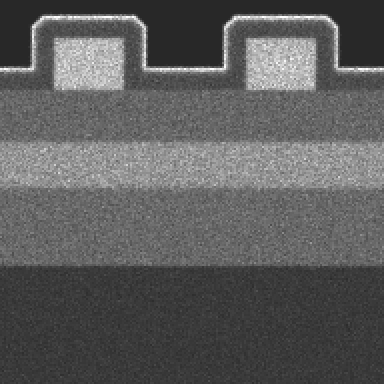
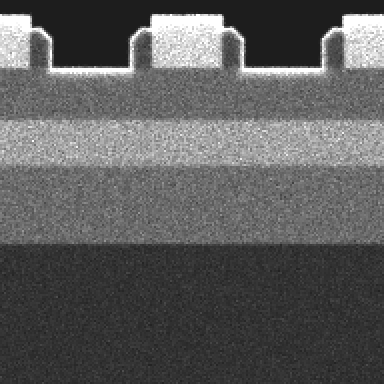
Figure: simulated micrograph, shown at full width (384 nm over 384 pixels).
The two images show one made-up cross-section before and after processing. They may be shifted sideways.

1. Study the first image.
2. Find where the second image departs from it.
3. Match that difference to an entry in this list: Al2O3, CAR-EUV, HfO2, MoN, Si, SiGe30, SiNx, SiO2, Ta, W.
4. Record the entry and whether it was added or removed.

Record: SiNx / removed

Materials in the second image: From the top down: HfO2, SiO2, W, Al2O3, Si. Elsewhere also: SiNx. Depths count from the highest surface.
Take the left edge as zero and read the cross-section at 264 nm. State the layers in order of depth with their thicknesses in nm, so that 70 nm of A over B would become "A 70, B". empty 52, SiO2 52, W 46, Al2O3 78, Si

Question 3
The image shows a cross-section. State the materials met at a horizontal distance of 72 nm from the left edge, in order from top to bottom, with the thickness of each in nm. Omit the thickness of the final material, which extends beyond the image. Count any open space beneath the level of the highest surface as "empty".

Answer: empty 52, SiO2 52, W 46, Al2O3 78, Si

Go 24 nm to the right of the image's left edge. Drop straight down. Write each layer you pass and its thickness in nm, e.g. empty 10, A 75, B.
HfO2 52, SiO2 52, W 46, Al2O3 78, Si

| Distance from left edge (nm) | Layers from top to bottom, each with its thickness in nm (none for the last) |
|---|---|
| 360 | HfO2 52, SiO2 52, W 46, Al2O3 78, Si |